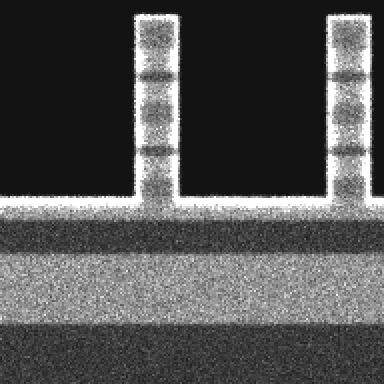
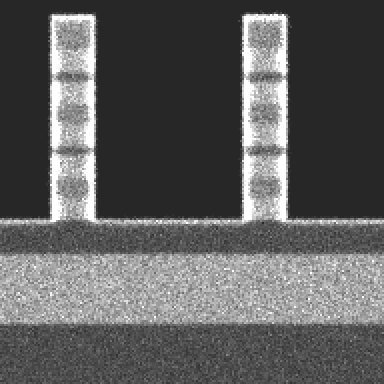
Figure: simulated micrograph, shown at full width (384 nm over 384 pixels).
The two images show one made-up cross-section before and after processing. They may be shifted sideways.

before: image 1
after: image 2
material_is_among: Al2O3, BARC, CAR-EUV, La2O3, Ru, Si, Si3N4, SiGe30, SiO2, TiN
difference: SiO2, removed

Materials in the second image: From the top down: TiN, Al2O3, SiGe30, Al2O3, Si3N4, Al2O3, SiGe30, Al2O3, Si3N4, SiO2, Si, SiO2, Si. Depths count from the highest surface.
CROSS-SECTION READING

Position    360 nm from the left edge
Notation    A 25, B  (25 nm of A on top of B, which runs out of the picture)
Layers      empty 204, Si 34, SiO2 70, Si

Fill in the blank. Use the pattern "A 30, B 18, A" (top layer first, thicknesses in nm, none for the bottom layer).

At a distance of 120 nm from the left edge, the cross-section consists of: empty 204, Si 34, SiO2 70, Si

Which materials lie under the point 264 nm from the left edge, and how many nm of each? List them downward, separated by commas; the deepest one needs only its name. TiN 34, Al2O3 22, SiGe30 10, Al2O3 22, Si3N4 20, Al2O3 22, SiGe30 10, Al2O3 22, Si3N4 20, SiO2 22, Si 34, SiO2 70, Si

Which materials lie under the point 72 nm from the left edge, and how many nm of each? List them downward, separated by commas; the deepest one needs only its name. TiN 34, Al2O3 22, SiGe30 10, Al2O3 22, Si3N4 20, Al2O3 22, SiGe30 10, Al2O3 22, Si3N4 20, SiO2 22, Si 34, SiO2 70, Si